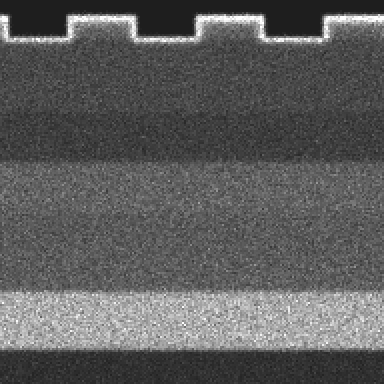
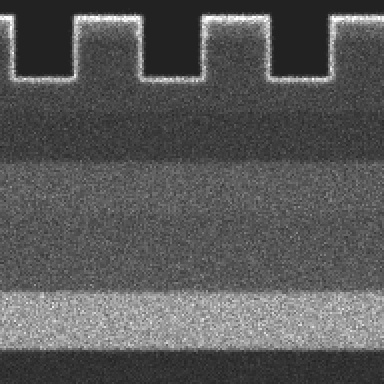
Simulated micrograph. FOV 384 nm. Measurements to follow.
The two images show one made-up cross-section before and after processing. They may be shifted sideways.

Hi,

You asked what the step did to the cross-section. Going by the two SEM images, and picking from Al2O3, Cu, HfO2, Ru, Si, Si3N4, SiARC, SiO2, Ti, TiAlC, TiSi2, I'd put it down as Si3N4, removed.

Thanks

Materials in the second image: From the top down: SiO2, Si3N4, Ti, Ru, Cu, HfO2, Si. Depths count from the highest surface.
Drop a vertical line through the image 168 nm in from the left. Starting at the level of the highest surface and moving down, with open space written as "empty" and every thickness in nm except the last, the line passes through empty 62, Si3N4 34, Ti 50, Ru 52, Cu 78, HfO2 58, Si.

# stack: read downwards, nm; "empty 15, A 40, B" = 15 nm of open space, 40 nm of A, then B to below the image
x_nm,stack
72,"empty 62, Si3N4 34, Ti 50, Ru 52, Cu 78, HfO2 58, Si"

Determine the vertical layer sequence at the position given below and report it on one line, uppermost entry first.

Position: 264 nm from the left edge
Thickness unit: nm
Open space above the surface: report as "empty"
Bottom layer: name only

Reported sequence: SiO2 22, Si3N4 74, Ti 50, Ru 52, Cu 78, HfO2 58, Si